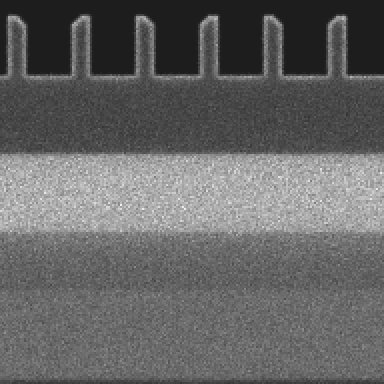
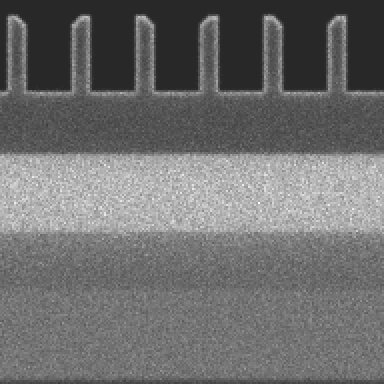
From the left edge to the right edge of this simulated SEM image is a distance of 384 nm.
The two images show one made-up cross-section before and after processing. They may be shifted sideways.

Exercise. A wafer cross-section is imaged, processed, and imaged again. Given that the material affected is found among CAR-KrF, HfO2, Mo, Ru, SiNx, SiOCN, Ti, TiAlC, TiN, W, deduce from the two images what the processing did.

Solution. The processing removed TiN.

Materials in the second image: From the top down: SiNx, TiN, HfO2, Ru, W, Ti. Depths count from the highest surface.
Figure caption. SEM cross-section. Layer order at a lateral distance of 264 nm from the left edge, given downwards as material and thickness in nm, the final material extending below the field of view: SiNx 60, TiN 78, HfO2 78, Ru 58, W 90, Ti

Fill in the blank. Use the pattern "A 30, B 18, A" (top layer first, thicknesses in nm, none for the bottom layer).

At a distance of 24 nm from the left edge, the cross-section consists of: empty 8, SiNx 52, TiN 78, HfO2 78, Ru 58, W 90, Ti